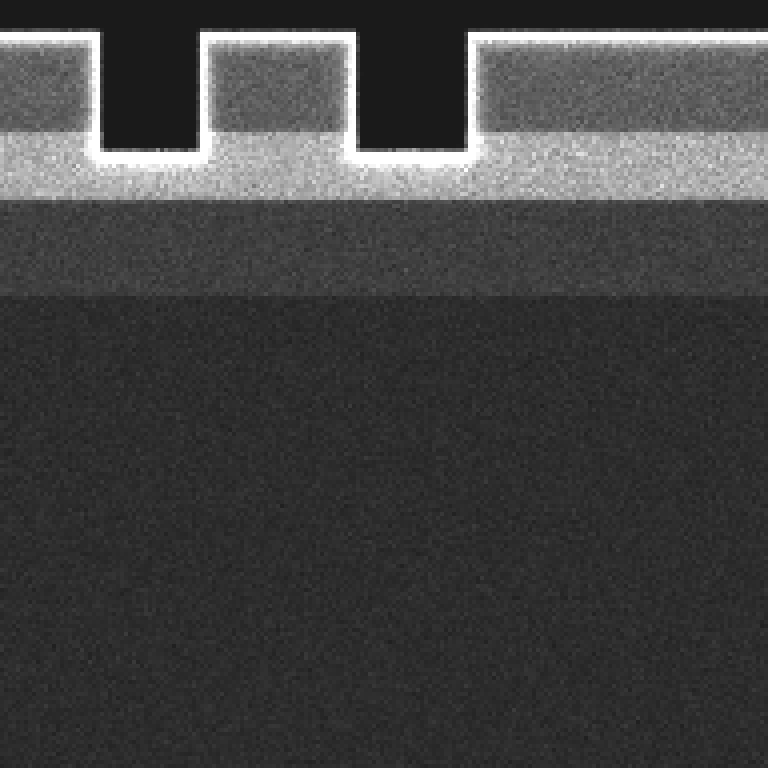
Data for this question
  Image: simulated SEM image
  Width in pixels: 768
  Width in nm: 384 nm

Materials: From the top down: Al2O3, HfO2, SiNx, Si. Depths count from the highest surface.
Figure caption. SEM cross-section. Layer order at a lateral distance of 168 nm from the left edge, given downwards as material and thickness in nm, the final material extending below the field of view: Al2O3 50, HfO2 34, SiNx 48, Si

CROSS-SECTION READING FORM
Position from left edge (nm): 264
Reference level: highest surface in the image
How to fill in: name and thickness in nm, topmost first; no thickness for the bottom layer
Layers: Al2O3 50, HfO2 34, SiNx 48, Si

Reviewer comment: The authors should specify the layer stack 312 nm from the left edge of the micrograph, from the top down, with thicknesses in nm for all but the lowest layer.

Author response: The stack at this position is Al2O3 50, HfO2 34, SiNx 48, Si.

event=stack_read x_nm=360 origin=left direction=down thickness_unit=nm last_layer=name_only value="Al2O3 50, HfO2 34, SiNx 48, Si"